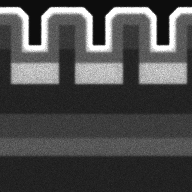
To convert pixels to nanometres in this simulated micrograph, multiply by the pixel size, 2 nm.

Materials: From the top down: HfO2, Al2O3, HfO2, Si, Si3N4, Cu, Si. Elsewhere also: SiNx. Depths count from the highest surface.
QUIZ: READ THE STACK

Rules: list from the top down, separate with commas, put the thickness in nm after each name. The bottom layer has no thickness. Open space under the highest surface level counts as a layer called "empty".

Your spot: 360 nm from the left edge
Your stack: HfO2 14, Al2O3 96, HfO2 42, Si 60, Si3N4 48, Cu 36, Si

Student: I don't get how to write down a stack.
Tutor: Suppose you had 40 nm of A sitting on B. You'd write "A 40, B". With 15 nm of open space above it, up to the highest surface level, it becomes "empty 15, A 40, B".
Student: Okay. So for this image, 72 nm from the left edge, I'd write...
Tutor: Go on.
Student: empty 76, HfO2 12, Al2O3 22, HfO2 42, Si 60, Si3N4 48, Cu 36, Si